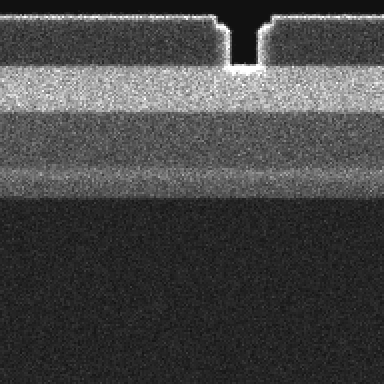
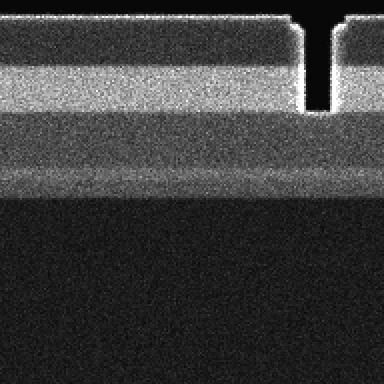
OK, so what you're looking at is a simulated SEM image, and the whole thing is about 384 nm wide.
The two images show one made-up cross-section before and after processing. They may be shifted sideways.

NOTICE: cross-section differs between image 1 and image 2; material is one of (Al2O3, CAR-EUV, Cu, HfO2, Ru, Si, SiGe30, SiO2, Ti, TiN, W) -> removed: HfO2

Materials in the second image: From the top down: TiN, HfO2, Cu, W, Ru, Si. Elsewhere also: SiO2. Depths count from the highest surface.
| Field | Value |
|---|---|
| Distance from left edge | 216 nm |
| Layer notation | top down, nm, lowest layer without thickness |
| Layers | TiN 50, HfO2 46, Cu 56, W 12, Ru 18, Si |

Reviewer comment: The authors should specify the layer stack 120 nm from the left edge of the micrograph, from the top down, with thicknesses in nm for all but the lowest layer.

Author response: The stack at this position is TiN 50, HfO2 46, Cu 56, W 12, Ru 18, Si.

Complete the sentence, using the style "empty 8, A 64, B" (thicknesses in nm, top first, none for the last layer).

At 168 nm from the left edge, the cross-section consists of TiN 50, HfO2 46, Cu 56, W 12, Ru 18, Si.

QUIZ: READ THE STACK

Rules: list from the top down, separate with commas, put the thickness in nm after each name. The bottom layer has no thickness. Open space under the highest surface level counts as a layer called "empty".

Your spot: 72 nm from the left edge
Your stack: TiN 50, HfO2 46, Cu 56, W 12, Ru 18, Si